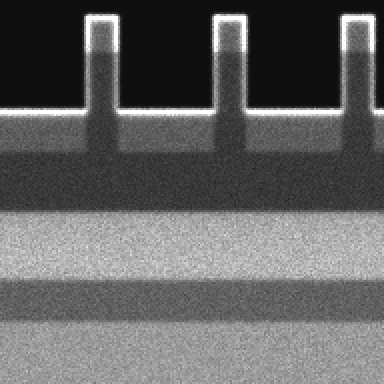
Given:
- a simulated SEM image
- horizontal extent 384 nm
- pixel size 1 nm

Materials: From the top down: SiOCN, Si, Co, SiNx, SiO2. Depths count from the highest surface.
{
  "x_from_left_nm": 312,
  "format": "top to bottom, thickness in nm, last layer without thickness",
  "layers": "empty 94, SiOCN 42, Si 60, Co 68, SiNx 42, SiO2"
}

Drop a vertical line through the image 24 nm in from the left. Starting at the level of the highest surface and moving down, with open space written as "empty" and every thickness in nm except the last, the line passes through empty 94, SiOCN 42, Si 60, Co 68, SiNx 42, SiO2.